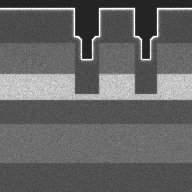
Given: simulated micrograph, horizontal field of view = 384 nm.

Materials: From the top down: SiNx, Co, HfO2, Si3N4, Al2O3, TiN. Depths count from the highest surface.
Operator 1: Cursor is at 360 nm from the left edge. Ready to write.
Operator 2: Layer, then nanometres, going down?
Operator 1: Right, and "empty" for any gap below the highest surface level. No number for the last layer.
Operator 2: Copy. SiNx 70, Co 62, HfO2 52, Si3N4 48, Al2O3 78, TiN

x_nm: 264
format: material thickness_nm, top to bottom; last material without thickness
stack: SiNx 70, Co 62, HfO2 52, Si3N4 48, Al2O3 78, TiN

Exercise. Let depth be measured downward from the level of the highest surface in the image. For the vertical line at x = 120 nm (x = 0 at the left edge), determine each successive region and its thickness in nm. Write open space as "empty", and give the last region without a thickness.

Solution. SiNx 70, Co 62, HfO2 52, Si3N4 48, Al2O3 78, TiN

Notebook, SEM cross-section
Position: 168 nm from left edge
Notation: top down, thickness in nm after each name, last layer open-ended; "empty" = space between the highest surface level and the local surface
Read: empty 102, SiNx 70, HfO2 12, Si3N4 48, Al2O3 78, TiN